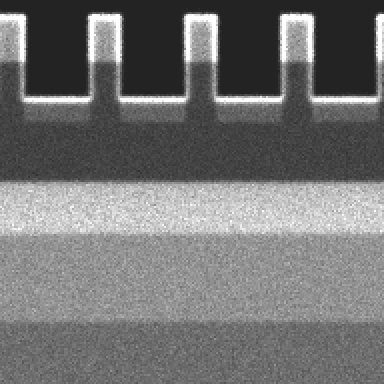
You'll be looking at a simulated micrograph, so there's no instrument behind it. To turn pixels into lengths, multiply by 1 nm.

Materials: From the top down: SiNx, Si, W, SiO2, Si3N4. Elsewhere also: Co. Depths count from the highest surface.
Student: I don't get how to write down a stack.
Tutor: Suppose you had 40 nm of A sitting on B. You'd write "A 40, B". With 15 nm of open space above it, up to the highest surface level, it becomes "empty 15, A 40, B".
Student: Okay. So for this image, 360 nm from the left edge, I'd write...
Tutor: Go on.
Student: empty 82, SiNx 24, Si 60, W 52, SiO2 88, Si3N4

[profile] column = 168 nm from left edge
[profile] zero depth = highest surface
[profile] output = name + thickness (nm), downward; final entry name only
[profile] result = empty 82, SiNx 24, Si 60, W 52, SiO2 88, Si3N4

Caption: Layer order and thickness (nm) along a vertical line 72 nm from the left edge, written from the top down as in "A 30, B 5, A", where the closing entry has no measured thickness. empty 82, SiNx 24, Si 60, W 52, SiO2 88, Si3N4